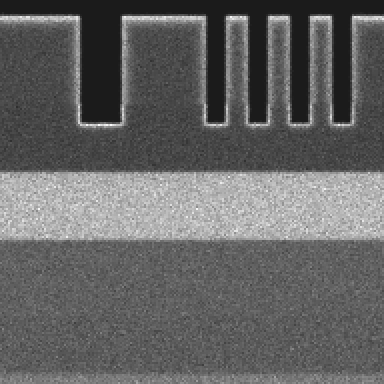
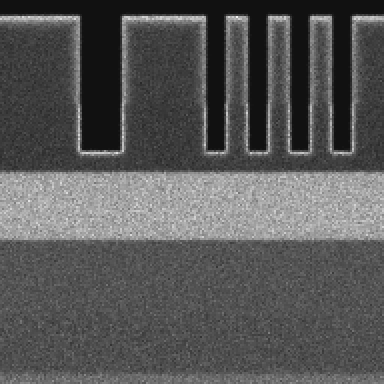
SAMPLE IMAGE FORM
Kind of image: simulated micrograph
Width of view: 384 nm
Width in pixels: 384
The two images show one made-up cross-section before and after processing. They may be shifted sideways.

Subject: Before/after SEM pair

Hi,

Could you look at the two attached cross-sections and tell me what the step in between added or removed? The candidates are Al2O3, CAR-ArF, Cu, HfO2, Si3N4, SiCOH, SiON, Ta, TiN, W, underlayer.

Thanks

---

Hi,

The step removed TiN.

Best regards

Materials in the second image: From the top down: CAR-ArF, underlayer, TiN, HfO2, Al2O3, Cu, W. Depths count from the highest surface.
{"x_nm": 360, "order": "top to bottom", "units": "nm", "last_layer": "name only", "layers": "CAR-ArF 66, underlayer 22, TiN 68, HfO2 68, Al2O3 76, Cu 58, W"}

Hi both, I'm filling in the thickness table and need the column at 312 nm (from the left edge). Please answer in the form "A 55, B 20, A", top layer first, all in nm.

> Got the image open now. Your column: CAR-ArF 66, underlayer 22, TiN 68, HfO2 68, Al2O3 76, Cu 58, W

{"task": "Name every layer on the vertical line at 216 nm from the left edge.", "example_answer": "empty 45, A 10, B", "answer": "empty 136, TiN 20, HfO2 68, Al2O3 76, Cu 58, W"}